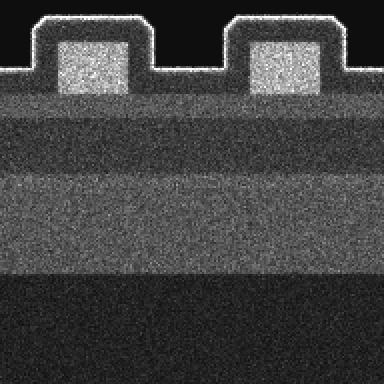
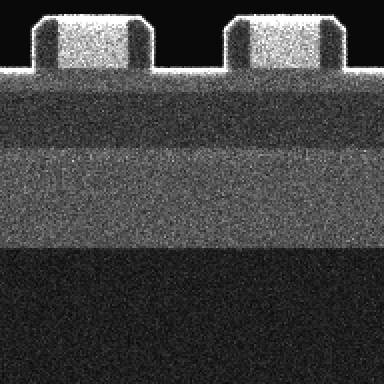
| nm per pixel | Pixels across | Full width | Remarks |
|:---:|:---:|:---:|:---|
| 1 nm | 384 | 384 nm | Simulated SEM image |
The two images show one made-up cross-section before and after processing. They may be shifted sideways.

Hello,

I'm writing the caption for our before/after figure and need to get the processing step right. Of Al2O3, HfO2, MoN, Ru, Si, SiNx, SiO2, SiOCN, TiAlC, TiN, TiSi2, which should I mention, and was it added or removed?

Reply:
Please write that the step removed SiNx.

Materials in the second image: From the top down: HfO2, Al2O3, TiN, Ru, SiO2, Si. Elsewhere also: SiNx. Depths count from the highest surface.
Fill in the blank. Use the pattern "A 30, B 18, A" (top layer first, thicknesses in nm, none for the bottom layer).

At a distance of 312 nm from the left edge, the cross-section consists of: HfO2 52, Al2O3 24, TiN 56, Ru 14, SiO2 86, Si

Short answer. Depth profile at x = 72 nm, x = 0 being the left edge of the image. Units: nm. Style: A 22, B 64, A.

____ HfO2 52, Al2O3 24, TiN 56, Ru 14, SiO2 86, Si